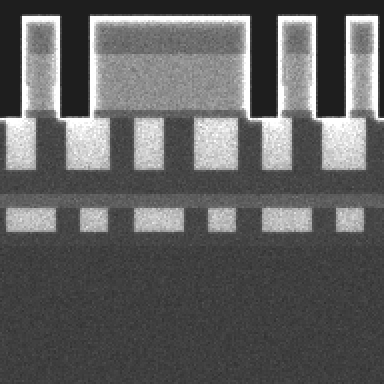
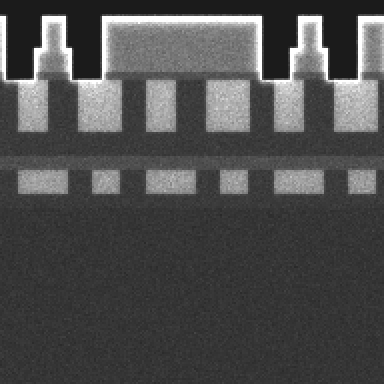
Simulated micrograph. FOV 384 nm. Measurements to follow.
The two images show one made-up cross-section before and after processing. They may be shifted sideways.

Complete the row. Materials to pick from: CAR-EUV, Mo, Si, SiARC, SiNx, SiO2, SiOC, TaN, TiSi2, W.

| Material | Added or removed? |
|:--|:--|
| SiARC | removed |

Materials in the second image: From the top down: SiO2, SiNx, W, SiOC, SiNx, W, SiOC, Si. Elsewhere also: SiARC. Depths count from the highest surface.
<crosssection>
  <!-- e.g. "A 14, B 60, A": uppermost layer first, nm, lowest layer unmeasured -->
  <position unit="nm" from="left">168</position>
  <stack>SiO2 56, SiNx 8, W 52, SiOC 24, SiNx 14, W 24, SiOC 14, Si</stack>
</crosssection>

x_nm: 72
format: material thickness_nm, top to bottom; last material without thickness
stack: empty 64, SiOC 76, SiNx 14, SiOC 38, Si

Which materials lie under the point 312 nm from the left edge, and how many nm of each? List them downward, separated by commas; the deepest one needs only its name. SiO2 56, SiNx 8, SiOC 76, SiNx 14, W 24, SiOC 14, Si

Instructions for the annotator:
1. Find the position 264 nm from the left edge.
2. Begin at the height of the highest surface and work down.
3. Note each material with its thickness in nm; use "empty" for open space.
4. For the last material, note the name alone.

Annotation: empty 64, SiOC 76, SiNx 14, SiOC 38, Si